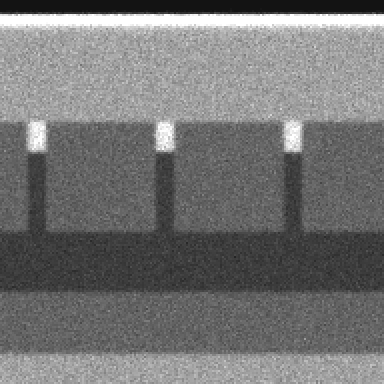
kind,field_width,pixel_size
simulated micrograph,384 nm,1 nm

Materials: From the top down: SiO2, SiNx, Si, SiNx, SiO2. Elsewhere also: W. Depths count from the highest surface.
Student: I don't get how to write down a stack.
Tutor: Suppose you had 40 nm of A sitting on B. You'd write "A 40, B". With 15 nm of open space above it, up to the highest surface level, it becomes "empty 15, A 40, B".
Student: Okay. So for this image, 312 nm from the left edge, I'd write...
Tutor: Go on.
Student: SiO2 106, SiNx 110, Si 60, SiNx 62, SiO2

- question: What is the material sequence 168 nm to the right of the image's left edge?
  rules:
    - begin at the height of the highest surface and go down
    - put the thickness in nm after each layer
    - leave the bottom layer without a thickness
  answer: SiO2 106, W 30, Si 140, SiNx 62, SiO2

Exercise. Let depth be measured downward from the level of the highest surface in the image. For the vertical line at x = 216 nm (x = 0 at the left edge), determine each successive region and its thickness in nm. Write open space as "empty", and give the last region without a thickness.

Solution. SiO2 106, SiNx 110, Si 60, SiNx 62, SiO2